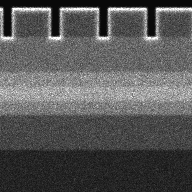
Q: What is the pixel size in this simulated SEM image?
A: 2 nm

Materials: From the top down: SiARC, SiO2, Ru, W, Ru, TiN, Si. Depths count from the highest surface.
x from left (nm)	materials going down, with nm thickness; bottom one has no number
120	SiARC 58, SiO2 70, Ru 30, W 28, Ru 28, TiN 70, Si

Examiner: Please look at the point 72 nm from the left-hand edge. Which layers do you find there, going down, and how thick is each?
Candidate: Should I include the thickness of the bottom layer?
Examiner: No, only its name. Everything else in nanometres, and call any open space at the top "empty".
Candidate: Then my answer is SiARC 58, SiO2 70, Ru 30, W 28, Ru 28, TiN 70, Si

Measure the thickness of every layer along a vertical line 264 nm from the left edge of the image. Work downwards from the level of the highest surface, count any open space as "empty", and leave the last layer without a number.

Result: SiARC 58, SiO2 70, Ru 30, W 28, Ru 28, TiN 70, Si